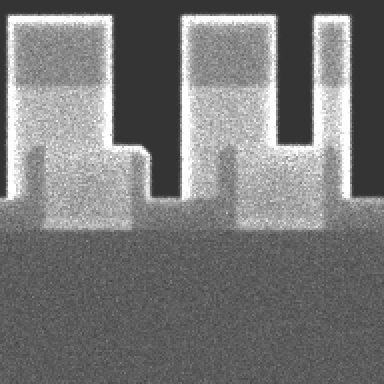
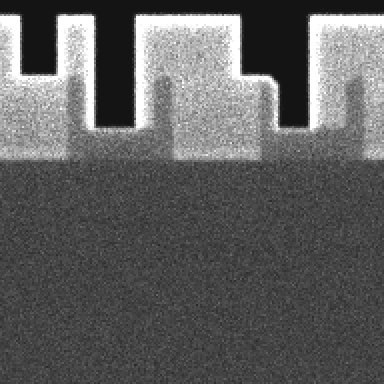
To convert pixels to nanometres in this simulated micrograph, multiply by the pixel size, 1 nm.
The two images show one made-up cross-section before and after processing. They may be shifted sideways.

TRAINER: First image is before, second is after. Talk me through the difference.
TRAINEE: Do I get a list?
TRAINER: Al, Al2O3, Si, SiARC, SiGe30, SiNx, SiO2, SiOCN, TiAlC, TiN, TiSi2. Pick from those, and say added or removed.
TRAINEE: removed: SiARC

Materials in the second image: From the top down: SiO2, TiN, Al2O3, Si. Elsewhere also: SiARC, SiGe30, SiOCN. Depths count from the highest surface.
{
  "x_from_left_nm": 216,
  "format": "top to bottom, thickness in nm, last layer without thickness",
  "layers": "SiO2 60, TiN 72, Al2O3 12, Si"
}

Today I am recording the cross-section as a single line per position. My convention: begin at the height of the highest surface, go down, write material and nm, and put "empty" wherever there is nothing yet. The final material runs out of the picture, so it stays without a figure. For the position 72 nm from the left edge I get SiO2 60, SiOCN 84, Si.